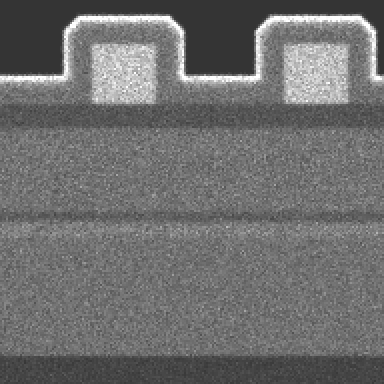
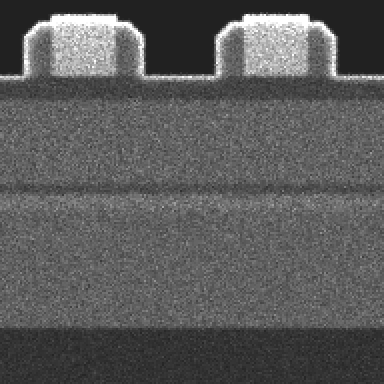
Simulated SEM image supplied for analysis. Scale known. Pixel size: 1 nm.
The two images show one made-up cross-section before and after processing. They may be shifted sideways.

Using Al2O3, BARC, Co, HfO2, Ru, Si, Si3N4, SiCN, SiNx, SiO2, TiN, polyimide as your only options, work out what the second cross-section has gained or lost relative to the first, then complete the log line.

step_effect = removed SiO2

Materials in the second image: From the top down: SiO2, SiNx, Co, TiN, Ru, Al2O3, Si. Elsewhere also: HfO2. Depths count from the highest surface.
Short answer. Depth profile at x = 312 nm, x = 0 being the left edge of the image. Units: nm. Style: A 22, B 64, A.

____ empty 6, SiO2 54, SiNx 24, Co 84, TiN 10, Ru 16, Al2O3 118, Si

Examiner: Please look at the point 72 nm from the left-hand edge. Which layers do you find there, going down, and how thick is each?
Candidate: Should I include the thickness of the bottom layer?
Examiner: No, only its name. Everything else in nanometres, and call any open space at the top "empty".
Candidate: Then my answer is HfO2 60, SiNx 24, Co 84, TiN 10, Ru 16, Al2O3 118, Si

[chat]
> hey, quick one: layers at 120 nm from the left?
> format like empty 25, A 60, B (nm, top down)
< empty 6, SiO2 54, SiNx 24, Co 84, TiN 10, Ru 16, Al2O3 118, Si